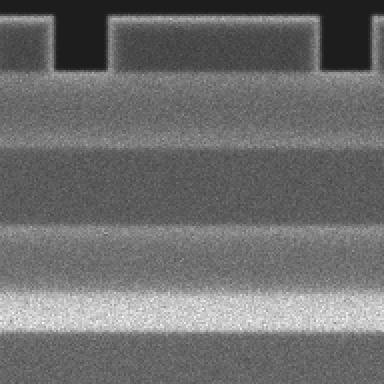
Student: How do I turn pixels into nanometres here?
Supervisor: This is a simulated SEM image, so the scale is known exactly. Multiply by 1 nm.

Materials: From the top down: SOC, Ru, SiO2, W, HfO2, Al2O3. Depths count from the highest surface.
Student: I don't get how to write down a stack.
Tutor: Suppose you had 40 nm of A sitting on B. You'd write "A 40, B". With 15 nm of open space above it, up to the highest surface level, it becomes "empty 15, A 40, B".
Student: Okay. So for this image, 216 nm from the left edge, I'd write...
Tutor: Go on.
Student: SOC 56, Ru 76, SiO2 78, W 68, HfO2 38, Al2O3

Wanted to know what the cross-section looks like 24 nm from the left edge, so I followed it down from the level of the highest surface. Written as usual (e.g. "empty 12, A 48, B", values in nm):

SOC 56, Ru 76, SiO2 78, W 68, HfO2 38, Al2O3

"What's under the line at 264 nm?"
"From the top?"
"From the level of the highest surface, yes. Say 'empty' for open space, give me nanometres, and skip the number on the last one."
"SOC 56, Ru 76, SiO2 78, W 68, HfO2 38, Al2O3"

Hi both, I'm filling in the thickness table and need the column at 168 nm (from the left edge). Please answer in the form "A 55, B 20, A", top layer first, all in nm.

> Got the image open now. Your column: SOC 56, Ru 76, SiO2 78, W 68, HfO2 38, Al2O3